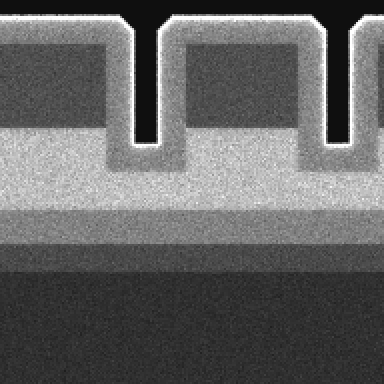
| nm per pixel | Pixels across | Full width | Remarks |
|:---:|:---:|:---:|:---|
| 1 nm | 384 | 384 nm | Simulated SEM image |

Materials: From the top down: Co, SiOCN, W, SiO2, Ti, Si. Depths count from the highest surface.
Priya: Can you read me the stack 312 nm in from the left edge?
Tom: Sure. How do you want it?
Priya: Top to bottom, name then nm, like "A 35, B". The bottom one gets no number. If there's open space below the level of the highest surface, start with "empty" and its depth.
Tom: empty 2, Co 154, W 38, SiO2 34, Ti 28, Si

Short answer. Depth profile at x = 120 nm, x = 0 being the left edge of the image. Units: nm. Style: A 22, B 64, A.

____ empty 2, Co 154, W 38, SiO2 34, Ti 28, Si